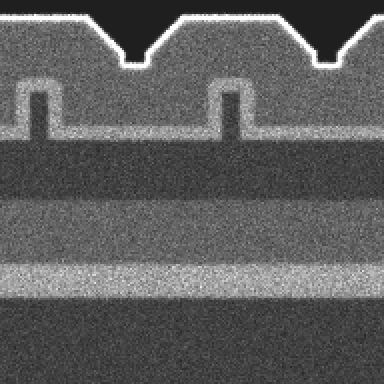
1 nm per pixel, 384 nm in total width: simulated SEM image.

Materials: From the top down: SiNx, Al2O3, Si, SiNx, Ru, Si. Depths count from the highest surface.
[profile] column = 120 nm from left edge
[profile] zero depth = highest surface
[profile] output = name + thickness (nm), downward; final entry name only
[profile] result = empty 34, SiNx 76, Al2O3 14, Si 60, SiNx 64, Ru 34, Si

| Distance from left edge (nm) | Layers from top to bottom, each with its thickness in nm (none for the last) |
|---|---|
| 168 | empty 14, SiNx 96, Al2O3 14, Si 60, SiNx 64, Ru 34, Si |